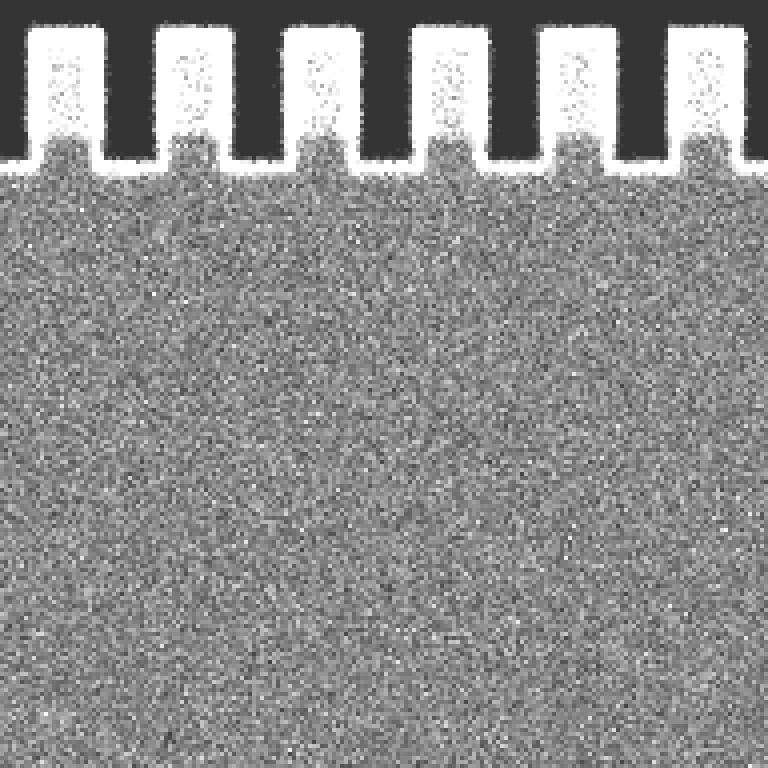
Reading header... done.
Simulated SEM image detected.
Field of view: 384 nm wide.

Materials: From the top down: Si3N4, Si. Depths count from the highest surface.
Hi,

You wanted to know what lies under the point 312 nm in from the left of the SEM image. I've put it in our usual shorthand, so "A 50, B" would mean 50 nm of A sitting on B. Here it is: empty 66, Si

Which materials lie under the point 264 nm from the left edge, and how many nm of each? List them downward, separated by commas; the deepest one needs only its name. empty 66, Si